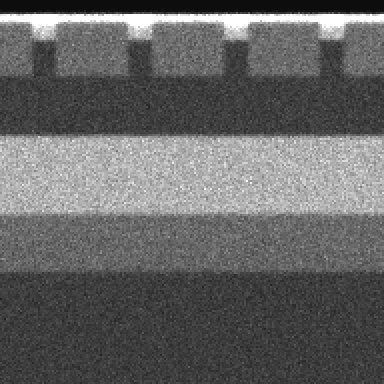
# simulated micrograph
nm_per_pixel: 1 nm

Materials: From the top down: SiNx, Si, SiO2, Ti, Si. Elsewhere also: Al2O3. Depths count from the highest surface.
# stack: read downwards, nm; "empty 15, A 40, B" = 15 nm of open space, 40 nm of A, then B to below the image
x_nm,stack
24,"SiNx 60, Si 60, SiO2 78, Ti 58, Si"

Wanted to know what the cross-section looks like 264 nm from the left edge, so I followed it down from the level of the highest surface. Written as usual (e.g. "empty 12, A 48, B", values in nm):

SiNx 60, Si 60, SiO2 78, Ti 58, Si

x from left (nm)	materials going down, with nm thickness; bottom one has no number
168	SiNx 60, Si 60, SiO2 78, Ti 58, Si